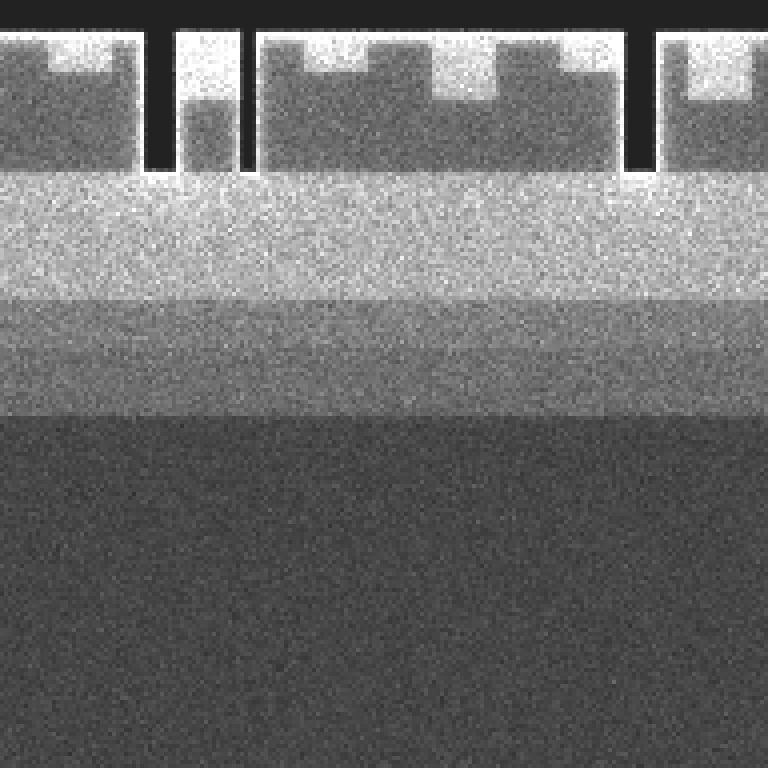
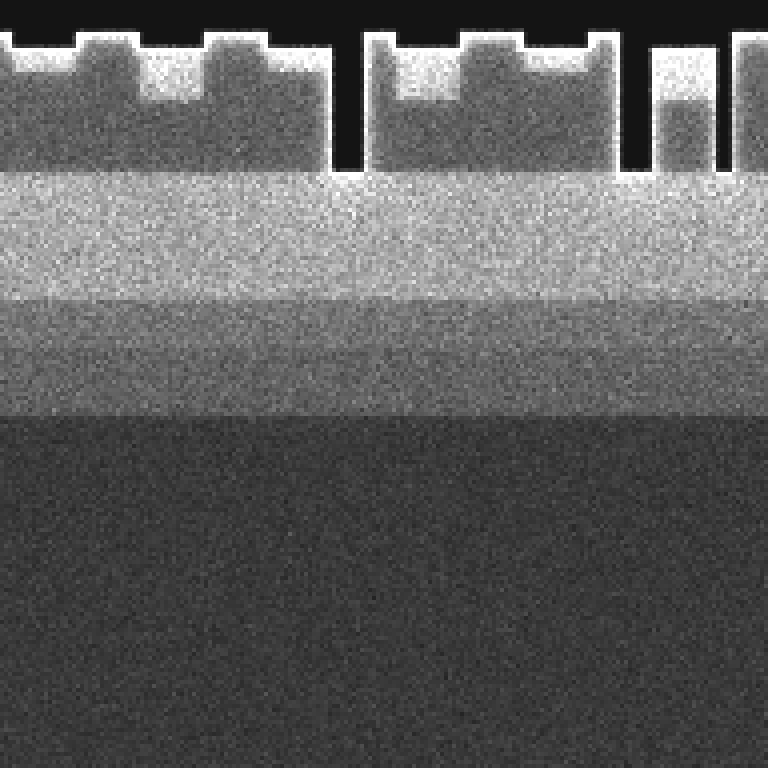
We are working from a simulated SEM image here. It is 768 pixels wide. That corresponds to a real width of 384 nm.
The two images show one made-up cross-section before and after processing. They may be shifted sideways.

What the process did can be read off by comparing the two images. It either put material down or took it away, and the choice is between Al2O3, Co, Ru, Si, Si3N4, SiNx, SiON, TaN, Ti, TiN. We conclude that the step removed Ru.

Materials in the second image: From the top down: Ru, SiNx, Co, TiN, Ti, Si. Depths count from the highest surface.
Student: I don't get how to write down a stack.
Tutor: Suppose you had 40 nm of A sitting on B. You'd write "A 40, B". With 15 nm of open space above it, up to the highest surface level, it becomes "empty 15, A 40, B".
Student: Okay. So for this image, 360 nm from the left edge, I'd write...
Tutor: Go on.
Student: empty 70, Co 64, TiN 24, Ti 34, Si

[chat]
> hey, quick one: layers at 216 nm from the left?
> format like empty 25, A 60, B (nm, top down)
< empty 8, Ru 26, SiNx 36, Co 64, TiN 24, Ti 34, Si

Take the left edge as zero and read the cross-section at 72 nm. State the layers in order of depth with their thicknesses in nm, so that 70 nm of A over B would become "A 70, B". empty 8, Ru 26, SiNx 36, Co 64, TiN 24, Ti 34, Si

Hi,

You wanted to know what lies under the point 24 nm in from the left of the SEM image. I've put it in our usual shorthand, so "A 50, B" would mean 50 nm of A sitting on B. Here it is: empty 8, Ru 12, SiNx 50, Co 64, TiN 24, Ti 34, Si